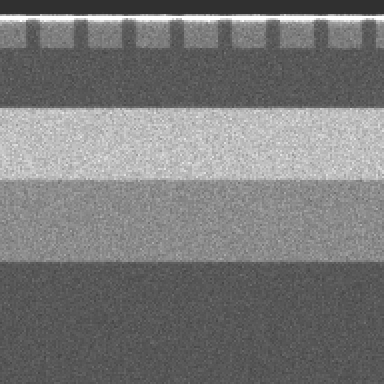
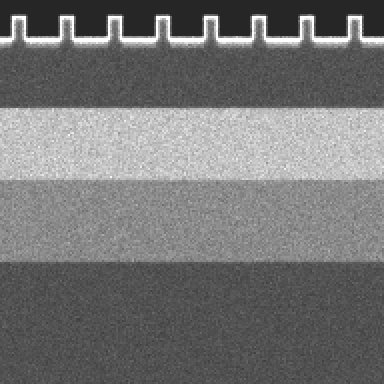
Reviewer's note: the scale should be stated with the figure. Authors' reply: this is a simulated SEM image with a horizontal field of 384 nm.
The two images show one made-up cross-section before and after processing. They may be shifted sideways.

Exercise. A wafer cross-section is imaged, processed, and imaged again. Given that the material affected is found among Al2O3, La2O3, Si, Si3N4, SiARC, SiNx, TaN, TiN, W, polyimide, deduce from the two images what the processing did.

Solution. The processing removed SiNx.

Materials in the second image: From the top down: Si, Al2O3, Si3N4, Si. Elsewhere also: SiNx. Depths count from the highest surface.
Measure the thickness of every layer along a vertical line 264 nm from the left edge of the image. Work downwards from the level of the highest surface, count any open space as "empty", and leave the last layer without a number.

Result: Si 92, Al2O3 72, Si3N4 82, Si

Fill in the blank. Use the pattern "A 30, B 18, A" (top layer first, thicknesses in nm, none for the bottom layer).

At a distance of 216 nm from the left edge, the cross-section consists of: Si 92, Al2O3 72, Si3N4 82, Si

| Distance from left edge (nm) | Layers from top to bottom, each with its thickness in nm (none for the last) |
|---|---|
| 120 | Si 92, Al2O3 72, Si3N4 82, Si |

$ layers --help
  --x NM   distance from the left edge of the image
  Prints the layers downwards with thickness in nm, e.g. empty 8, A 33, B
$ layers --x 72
Si 92, Al2O3 72, Si3N4 82, Si